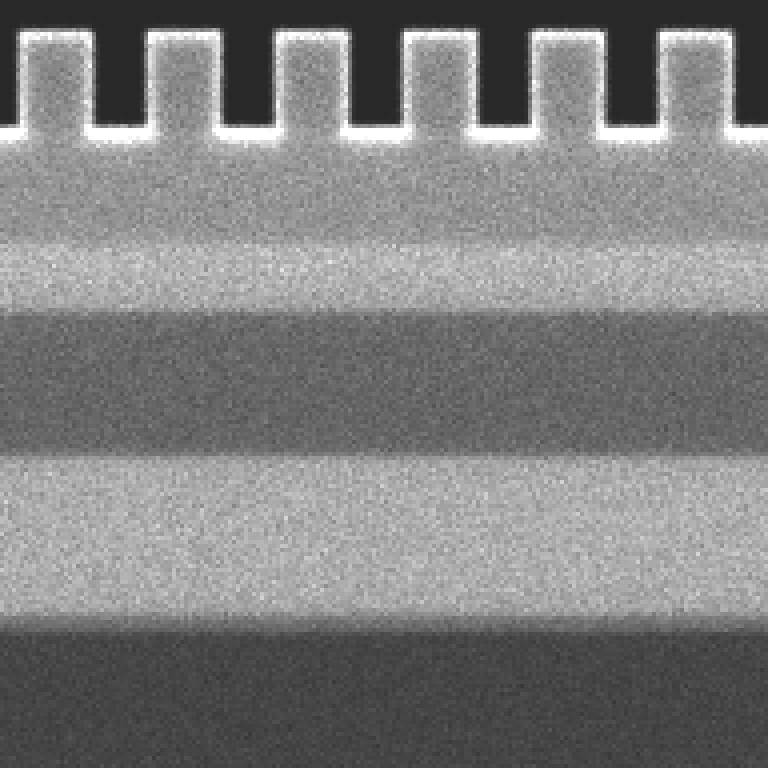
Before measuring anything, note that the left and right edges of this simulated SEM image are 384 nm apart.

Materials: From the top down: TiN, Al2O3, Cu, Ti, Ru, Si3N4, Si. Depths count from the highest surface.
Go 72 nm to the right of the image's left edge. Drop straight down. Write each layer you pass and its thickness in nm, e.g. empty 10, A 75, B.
empty 48, Al2O3 58, Cu 34, Ti 72, Ru 80, Si3N4 8, Si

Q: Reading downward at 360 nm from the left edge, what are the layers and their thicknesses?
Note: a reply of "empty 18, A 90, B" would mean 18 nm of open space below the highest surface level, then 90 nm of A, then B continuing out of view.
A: TiN 48, Al2O3 58, Cu 34, Ti 72, Ru 80, Si3N4 8, Si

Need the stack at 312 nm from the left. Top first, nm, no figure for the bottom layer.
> empty 48, Al2O3 58, Cu 34, Ti 72, Ru 80, Si3N4 8, Si